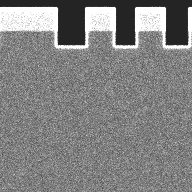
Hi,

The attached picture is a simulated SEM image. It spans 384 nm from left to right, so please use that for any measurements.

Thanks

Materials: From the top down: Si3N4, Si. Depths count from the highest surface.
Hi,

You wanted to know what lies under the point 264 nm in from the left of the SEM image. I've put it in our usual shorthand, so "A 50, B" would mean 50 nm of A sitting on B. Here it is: empty 76, Si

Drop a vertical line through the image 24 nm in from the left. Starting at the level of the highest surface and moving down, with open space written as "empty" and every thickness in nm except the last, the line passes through Si3N4 46, Si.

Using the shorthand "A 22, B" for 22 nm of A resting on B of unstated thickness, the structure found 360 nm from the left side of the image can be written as empty 76, Si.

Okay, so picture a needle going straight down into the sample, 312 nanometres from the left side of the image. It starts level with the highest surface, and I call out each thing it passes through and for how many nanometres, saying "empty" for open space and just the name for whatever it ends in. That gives Si3N4 46, Si